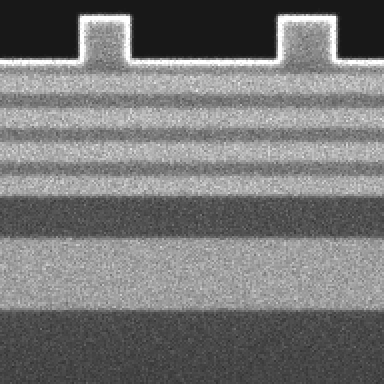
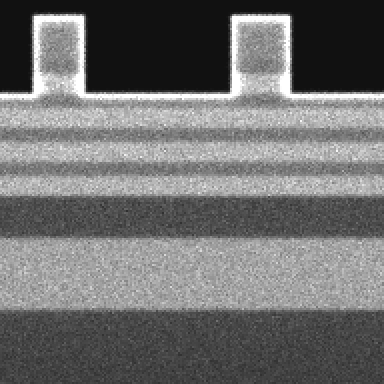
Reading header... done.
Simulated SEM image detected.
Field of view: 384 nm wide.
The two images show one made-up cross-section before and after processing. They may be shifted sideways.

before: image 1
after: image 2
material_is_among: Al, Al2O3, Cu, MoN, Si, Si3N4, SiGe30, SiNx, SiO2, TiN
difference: Al2O3 and SiNx, removed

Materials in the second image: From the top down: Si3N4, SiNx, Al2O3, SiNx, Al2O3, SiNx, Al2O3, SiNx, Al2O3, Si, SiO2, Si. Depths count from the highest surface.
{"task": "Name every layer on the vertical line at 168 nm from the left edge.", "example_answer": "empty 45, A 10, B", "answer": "empty 78, SiNx 14, Al2O3 20, SiNx 14, Al2O3 20, SiNx 14, Al2O3 20, Si 42, SiO2 72, Si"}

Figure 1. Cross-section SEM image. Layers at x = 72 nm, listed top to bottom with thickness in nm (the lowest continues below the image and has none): Si3N4 44, SiNx 14, Al2O3 20, SiNx 14, Al2O3 20, SiNx 14, Al2O3 20, SiNx 14, Al2O3 20, Si 42, SiO2 72, Si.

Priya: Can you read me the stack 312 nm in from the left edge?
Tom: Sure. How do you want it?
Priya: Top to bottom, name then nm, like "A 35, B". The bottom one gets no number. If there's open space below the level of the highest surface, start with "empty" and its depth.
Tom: empty 78, SiNx 14, Al2O3 20, SiNx 14, Al2O3 20, SiNx 14, Al2O3 20, Si 42, SiO2 72, Si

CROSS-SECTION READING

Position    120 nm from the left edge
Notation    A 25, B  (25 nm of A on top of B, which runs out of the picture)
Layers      empty 78, SiNx 14, Al2O3 20, SiNx 14, Al2O3 20, SiNx 14, Al2O3 20, Si 42, SiO2 72, Si